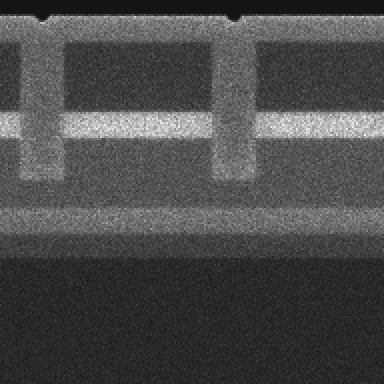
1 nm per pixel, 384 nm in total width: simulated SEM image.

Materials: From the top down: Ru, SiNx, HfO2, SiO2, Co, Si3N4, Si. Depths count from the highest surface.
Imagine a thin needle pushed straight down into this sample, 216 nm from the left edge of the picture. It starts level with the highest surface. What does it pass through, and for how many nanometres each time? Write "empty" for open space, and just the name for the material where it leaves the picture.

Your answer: Ru 164, SiO2 28, Co 26, Si3N4 24, Si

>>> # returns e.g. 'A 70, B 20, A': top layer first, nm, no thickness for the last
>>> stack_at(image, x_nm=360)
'Ru 26, SiNx 70, HfO2 26, SiO2 70, Co 26, Si3N4 24, Si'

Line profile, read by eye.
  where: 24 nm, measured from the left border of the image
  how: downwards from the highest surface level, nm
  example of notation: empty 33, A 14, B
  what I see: Ru 164, SiO2 28, Co 26, Si3N4 24, Si